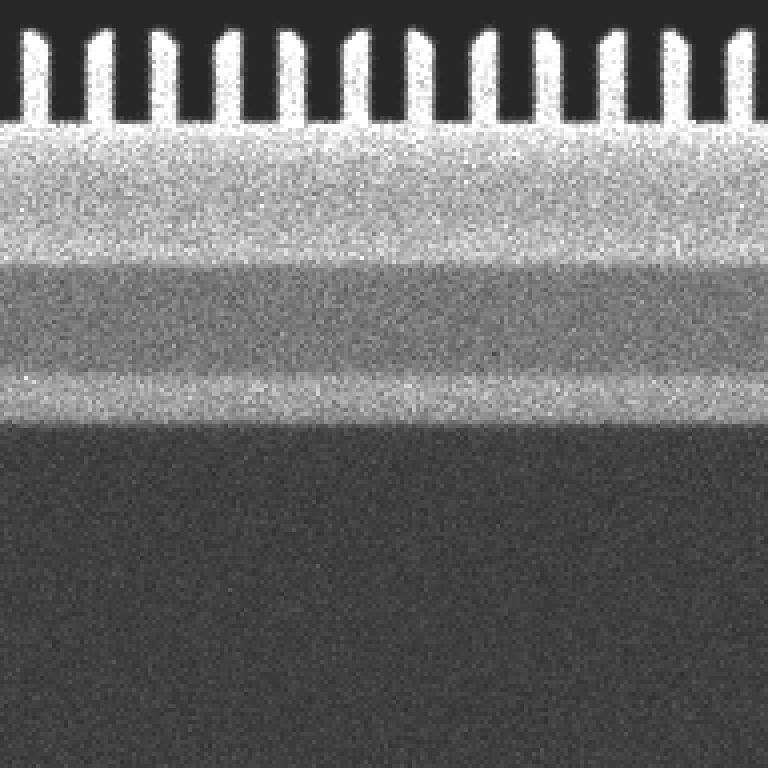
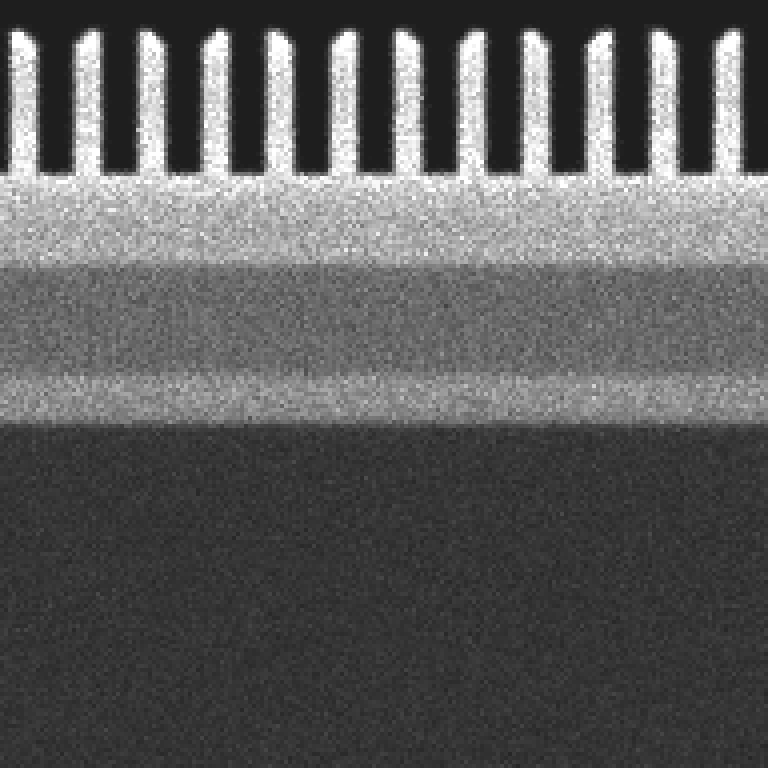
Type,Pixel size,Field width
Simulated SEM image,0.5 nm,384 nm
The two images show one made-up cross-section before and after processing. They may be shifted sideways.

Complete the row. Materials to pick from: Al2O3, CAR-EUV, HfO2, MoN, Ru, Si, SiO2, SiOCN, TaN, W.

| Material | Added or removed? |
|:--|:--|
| W | removed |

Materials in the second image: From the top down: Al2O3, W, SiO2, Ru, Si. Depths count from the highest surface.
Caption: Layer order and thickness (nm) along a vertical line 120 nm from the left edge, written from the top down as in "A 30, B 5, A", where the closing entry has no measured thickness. empty 72, W 44, SiO2 56, Ru 24, Si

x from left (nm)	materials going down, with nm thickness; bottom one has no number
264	Al2O3 46, W 70, SiO2 56, Ru 24, Si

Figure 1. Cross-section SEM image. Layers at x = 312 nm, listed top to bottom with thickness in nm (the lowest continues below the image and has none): empty 72, W 44, SiO2 56, Ru 24, Si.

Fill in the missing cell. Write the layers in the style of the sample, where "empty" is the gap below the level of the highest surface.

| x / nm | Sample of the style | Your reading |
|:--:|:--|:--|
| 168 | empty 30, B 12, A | empty 4, Al2O3 42, W 70, SiO2 56, Ru 24, Si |